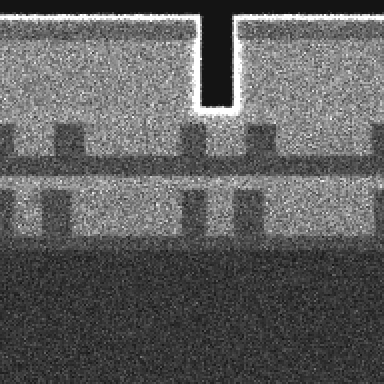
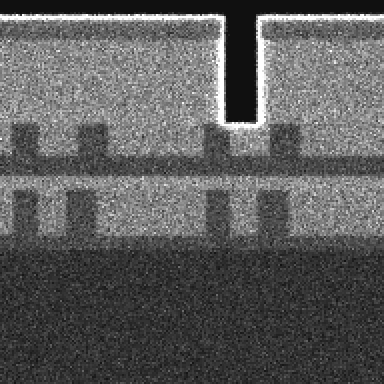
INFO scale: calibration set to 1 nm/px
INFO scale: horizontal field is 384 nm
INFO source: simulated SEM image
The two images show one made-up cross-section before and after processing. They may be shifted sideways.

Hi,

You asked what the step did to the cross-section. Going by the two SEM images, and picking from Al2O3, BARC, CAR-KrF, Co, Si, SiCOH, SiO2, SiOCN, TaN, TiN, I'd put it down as Al2O3, removed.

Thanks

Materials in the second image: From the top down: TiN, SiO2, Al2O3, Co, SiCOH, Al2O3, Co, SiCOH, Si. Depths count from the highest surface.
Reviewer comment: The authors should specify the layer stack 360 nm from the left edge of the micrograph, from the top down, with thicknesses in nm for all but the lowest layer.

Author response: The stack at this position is TiN 24, SiO2 68, Al2O3 16, Co 32, SiCOH 20, Al2O3 14, Co 46, SiCOH 14, Si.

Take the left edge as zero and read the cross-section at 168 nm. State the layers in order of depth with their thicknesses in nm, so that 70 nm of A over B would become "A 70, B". TiN 24, SiO2 68, Al2O3 16, Co 32, SiCOH 20, Al2O3 14, Co 46, SiCOH 14, Si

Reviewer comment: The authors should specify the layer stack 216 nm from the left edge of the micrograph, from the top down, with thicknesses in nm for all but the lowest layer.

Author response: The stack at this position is TiN 24, SiO2 68, Al2O3 16, SiCOH 52, Al2O3 14, SiCOH 60, Si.